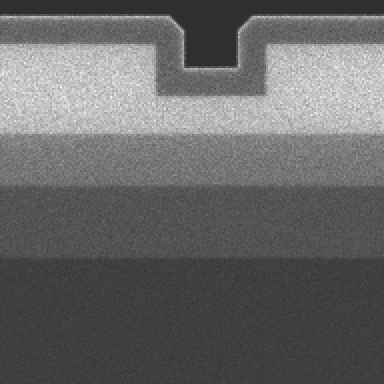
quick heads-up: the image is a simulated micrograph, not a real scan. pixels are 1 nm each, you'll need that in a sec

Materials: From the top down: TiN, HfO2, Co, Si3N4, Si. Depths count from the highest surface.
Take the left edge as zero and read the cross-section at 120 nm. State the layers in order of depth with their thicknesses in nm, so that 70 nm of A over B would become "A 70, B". TiN 28, HfO2 90, Co 52, Si3N4 72, Si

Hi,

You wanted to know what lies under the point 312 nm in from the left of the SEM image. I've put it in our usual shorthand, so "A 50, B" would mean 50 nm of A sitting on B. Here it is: TiN 28, HfO2 90, Co 52, Si3N4 72, Si